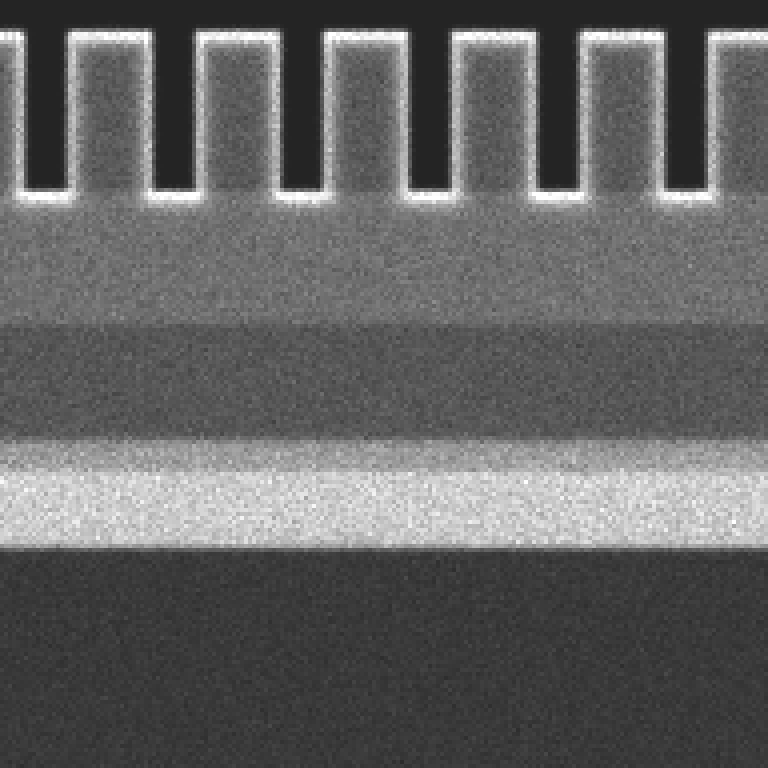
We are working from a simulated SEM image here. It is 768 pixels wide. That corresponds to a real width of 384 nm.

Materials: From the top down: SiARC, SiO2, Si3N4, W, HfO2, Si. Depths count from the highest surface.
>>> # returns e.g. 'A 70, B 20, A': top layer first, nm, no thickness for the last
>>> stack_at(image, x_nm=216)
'empty 80, SiO2 66, Si3N4 58, W 16, HfO2 38, Si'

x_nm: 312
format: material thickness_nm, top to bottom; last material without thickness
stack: SiARC 80, SiO2 66, Si3N4 58, W 16, HfO2 38, Si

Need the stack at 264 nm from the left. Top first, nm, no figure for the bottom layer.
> SiARC 80, SiO2 66, Si3N4 58, W 16, HfO2 38, Si